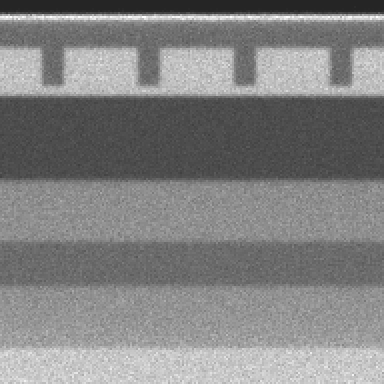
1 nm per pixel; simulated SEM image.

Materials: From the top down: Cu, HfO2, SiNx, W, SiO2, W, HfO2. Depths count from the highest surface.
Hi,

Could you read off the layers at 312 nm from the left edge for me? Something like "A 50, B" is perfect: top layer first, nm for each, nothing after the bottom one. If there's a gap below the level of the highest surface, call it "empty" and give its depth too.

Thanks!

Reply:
Cu 32, HfO2 48, SiNx 84, W 62, SiO2 44, W 62, HfO2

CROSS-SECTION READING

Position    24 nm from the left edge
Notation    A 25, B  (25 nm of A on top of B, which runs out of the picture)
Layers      Cu 32, HfO2 48, SiNx 84, W 62, SiO2 44, W 62, HfO2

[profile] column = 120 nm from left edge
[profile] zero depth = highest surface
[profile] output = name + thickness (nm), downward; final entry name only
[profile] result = Cu 32, HfO2 48, SiNx 84, W 62, SiO2 44, W 62, HfO2